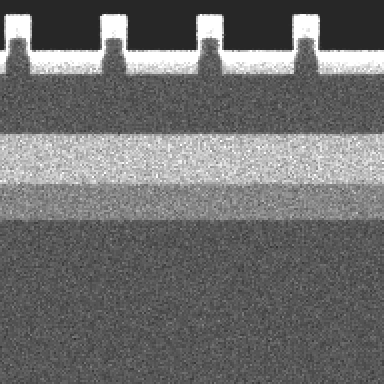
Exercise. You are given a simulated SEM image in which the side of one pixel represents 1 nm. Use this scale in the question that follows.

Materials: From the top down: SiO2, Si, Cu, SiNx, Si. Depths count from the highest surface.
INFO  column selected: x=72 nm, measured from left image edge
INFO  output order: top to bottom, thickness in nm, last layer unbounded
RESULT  empty 36, SiO2 22, Si 60, Cu 50, SiNx 36, Si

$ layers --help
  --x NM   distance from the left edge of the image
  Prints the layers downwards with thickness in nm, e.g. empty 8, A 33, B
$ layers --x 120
SiO2 22, Si 96, Cu 50, SiNx 36, Si